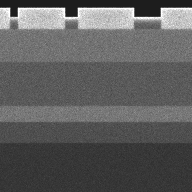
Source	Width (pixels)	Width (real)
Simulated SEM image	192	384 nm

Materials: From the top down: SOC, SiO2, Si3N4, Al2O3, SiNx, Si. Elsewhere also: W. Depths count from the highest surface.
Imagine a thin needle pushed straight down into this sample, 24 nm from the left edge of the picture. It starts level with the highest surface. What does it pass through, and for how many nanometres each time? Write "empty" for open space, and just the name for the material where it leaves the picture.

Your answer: empty 18, SOC 24, SiO2 66, Si3N4 88, Al2O3 32, SiNx 42, Si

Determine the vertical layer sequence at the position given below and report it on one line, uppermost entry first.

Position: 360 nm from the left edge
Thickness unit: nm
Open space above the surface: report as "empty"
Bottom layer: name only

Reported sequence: W 42, SiO2 66, Si3N4 88, Al2O3 32, SiNx 42, Si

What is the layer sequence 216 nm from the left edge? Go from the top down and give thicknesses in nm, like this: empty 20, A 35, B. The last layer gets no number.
W 42, SiO2 66, Si3N4 88, Al2O3 32, SiNx 42, Si